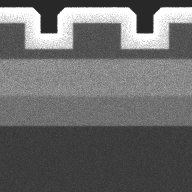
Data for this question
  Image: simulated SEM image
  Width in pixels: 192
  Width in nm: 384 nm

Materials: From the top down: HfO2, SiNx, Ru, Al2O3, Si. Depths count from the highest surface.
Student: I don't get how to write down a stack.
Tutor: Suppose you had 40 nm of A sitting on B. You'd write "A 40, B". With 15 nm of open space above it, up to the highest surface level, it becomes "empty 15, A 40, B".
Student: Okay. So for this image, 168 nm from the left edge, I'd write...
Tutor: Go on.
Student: HfO2 30, SiNx 72, Ru 74, Al2O3 60, Si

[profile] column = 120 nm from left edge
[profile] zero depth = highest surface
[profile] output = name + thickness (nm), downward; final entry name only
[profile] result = empty 10, HfO2 72, SiNx 20, Ru 74, Al2O3 60, Si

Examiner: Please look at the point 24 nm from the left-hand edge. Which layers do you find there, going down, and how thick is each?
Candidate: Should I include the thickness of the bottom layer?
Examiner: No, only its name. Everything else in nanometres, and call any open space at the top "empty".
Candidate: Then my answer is HfO2 30, SiNx 72, Ru 74, Al2O3 60, Si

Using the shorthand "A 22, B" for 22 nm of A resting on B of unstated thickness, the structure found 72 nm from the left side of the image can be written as empty 8, HfO2 74, SiNx 20, Ru 74, Al2O3 60, Si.